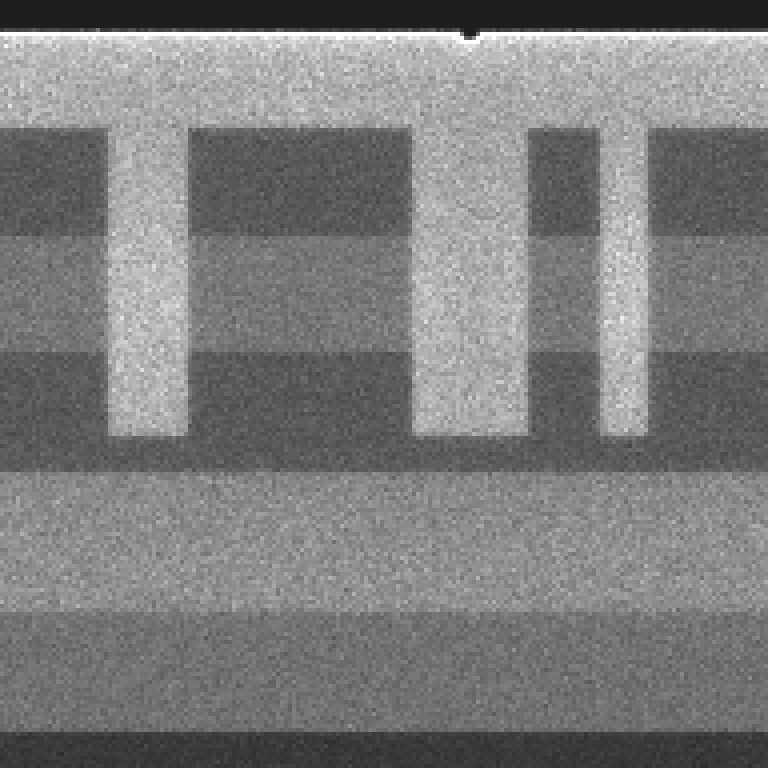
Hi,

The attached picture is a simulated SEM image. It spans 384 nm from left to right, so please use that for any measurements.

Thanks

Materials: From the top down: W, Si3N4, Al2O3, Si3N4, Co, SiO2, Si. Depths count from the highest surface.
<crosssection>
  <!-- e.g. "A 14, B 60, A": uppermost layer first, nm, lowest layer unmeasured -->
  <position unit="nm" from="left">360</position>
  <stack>W 48, Si3N4 54, Al2O3 58, Si3N4 60, Co 70, SiO2 60, Si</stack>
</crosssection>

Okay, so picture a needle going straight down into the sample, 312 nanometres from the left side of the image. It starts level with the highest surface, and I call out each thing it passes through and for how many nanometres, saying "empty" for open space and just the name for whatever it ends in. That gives W 202, Si3N4 18, Co 70, SiO2 60, Si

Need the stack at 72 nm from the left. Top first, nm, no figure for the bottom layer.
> W 202, Si3N4 18, Co 70, SiO2 60, Si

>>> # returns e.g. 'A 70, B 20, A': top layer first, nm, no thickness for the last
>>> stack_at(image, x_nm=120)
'W 48, Si3N4 54, Al2O3 58, Si3N4 60, Co 70, SiO2 60, Si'